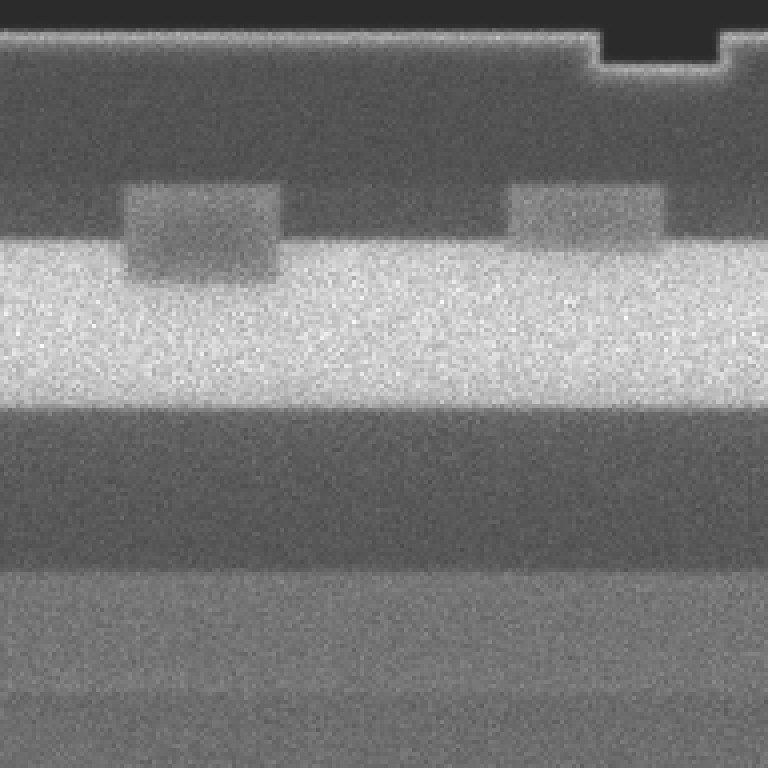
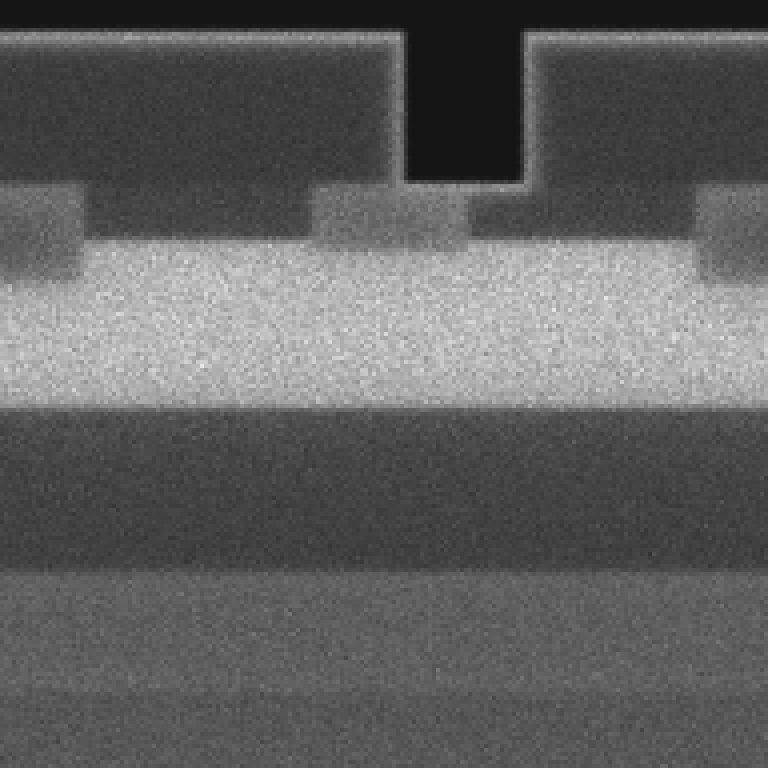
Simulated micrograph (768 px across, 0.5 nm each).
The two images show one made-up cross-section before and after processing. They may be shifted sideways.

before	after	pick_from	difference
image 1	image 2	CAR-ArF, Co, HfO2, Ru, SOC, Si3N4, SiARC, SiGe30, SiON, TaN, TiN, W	SOC removed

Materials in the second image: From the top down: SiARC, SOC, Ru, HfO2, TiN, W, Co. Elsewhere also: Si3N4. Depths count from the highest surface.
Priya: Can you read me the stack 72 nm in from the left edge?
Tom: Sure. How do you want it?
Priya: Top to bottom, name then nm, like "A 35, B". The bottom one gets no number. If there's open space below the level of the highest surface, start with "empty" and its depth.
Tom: SiARC 16, SOC 60, Si3N4 28, HfO2 84, TiN 82, W 60, Co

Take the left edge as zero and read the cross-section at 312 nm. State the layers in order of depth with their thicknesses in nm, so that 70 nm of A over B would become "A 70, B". SiARC 16, SOC 60, Si3N4 28, HfO2 84, TiN 82, W 60, Co